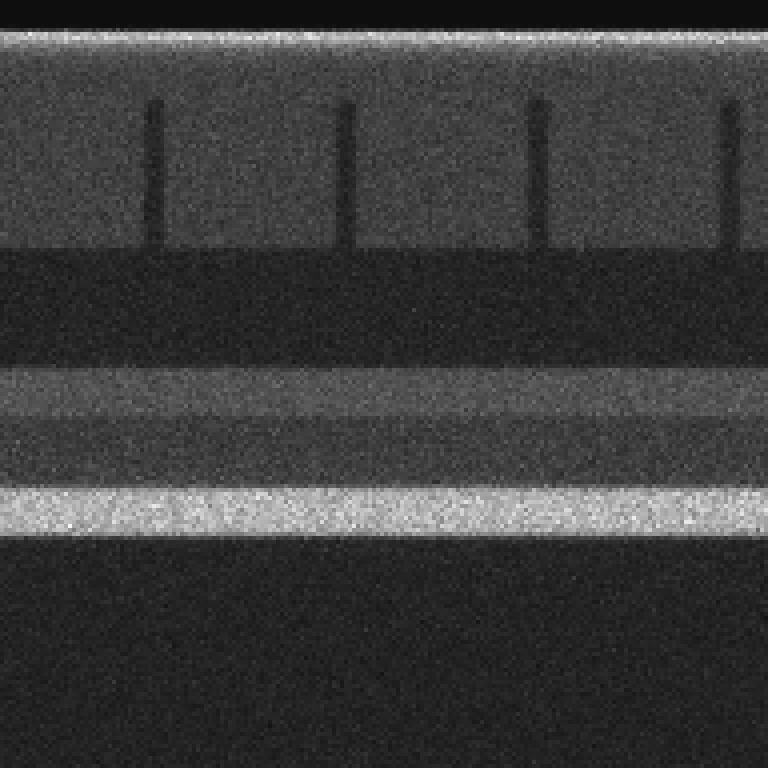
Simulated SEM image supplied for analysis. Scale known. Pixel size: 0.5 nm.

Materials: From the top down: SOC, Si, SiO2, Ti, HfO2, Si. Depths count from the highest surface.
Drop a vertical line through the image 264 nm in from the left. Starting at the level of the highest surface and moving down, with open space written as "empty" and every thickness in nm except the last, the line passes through SOC 34, Si 134, SiO2 24, Ti 36, HfO2 24, Si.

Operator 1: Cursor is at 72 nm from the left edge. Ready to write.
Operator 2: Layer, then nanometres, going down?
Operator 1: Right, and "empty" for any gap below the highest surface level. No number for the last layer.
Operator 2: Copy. SOC 34, Si 134, SiO2 24, Ti 36, HfO2 24, Si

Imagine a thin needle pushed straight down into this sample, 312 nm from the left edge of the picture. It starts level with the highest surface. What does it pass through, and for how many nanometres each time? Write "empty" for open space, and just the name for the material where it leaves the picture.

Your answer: SOC 108, Si 60, SiO2 24, Ti 36, HfO2 24, Si